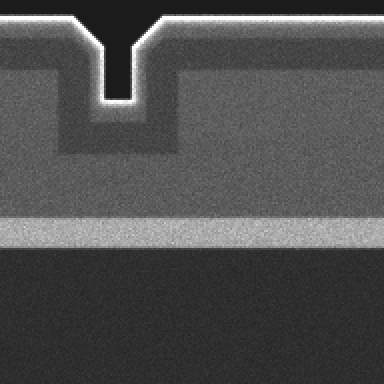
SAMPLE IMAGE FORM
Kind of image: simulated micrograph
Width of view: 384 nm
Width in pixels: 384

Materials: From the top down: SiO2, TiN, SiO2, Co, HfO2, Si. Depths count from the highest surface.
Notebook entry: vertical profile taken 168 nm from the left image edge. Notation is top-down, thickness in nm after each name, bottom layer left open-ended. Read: SiO2 22, TiN 116, Co 64, HfO2 30, Si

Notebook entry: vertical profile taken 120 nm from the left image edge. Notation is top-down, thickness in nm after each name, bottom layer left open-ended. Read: empty 84, SiO2 22, TiN 32, Co 64, HfO2 30, Si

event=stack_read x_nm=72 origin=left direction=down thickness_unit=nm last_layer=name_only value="SiO2 22, TiN 116, Co 64, HfO2 30, Si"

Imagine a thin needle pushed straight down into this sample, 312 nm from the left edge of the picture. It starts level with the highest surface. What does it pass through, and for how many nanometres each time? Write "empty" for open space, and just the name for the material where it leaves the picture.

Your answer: SiO2 22, TiN 32, SiO2 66, Co 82, HfO2 30, Si